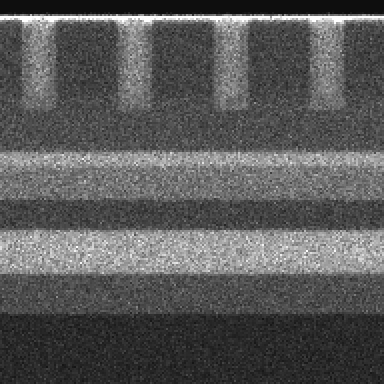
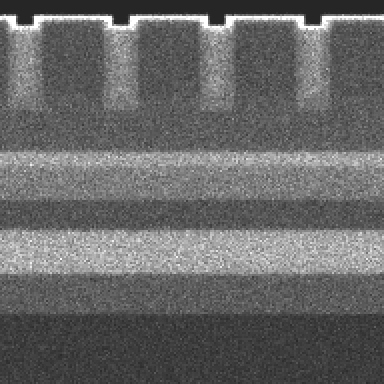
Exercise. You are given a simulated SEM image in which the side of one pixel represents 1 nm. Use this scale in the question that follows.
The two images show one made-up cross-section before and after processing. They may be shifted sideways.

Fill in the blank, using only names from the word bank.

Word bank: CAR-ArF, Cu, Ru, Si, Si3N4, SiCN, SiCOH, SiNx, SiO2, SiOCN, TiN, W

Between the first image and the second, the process removed Ru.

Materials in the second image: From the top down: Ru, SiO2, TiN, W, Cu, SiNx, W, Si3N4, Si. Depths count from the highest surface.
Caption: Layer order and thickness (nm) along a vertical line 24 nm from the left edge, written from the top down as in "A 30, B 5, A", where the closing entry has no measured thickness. empty 10, Ru 70, SiO2 14, TiN 42, W 14, Cu 34, SiNx 30, W 44, Si3N4 40, Si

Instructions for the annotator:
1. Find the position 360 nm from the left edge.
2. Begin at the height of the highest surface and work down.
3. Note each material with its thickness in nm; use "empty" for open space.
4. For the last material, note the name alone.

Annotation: SiNx 80, TiN 56, W 14, Cu 34, SiNx 30, W 44, Si3N4 40, Si